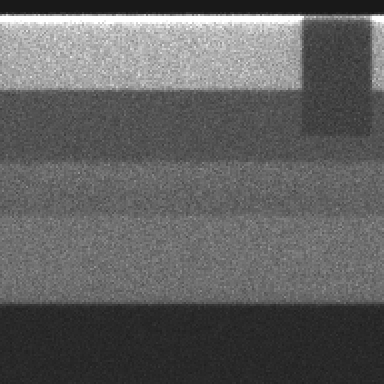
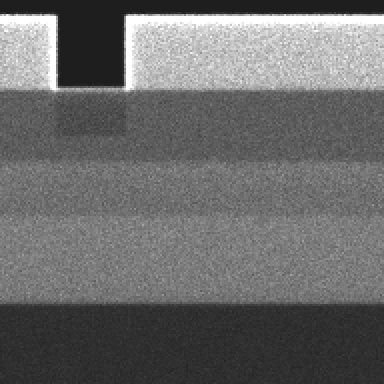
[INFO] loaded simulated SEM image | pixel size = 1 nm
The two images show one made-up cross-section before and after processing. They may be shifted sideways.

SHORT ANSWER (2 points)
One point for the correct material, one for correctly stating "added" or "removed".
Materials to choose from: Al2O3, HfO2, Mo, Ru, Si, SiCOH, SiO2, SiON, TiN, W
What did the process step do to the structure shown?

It removed TiN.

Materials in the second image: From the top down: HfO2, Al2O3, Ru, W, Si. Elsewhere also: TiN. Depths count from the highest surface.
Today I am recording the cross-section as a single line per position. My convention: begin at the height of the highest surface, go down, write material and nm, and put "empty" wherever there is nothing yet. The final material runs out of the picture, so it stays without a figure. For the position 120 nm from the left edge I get empty 72, TiN 48, Al2O3 26, Ru 54, W 88, Si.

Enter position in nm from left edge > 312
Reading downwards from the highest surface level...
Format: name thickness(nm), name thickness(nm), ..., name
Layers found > HfO2 74, Al2O3 72, Ru 54, W 88, Si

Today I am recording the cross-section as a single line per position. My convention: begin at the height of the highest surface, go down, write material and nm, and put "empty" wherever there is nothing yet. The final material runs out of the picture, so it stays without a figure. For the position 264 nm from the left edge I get HfO2 74, Al2O3 72, Ru 54, W 88, Si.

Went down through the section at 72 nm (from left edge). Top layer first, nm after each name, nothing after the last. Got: empty 72, TiN 48, Al2O3 26, Ru 54, W 88, Si